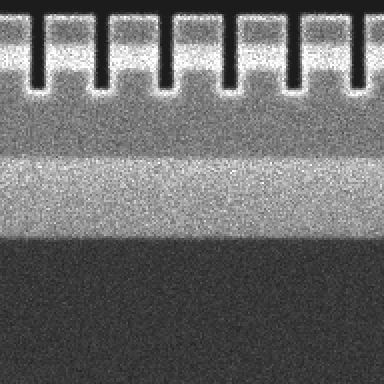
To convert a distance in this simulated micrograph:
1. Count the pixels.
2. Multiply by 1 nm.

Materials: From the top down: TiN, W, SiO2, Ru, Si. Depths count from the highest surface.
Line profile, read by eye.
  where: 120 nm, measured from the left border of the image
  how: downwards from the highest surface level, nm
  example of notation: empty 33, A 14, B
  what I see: TiN 28, W 26, SiO2 88, Ru 80, Si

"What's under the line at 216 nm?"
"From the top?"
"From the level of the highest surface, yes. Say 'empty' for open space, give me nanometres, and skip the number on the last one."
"TiN 28, W 26, SiO2 88, Ru 80, Si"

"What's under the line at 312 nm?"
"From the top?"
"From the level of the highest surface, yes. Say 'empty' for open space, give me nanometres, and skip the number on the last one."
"TiN 28, W 26, SiO2 88, Ru 80, Si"